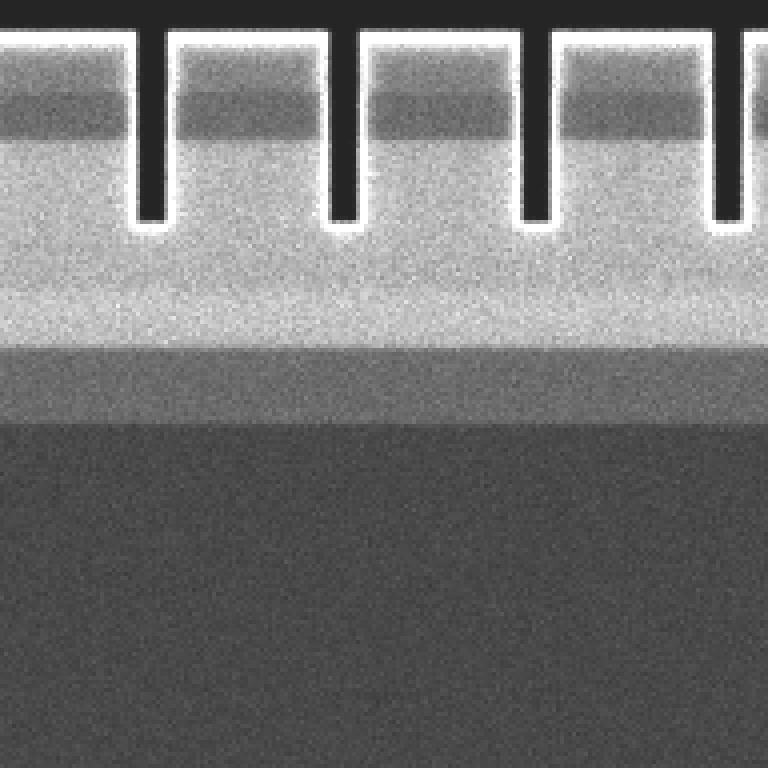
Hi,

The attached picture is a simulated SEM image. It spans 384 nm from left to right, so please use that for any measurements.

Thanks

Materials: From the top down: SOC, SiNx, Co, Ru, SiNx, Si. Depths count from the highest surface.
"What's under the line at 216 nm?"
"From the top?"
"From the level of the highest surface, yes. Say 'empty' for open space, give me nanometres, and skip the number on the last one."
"SOC 30, SiNx 24, Co 76, Ru 28, SiNx 38, Si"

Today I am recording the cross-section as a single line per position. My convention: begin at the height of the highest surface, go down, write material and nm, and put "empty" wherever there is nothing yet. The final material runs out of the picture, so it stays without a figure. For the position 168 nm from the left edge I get empty 96, Co 34, Ru 28, SiNx 38, Si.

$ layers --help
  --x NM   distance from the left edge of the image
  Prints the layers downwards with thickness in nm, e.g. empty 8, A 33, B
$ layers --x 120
SOC 30, SiNx 24, Co 76, Ru 28, SiNx 38, Si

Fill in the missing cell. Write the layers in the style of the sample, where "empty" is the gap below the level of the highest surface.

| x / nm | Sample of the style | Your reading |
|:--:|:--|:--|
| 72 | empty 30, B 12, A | empty 96, Co 34, Ru 28, SiNx 38, Si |